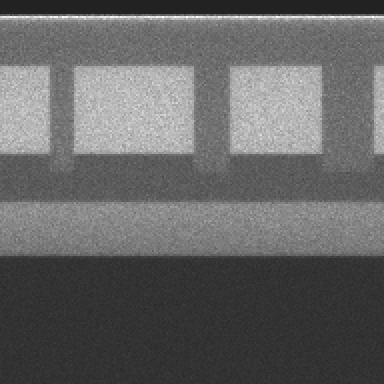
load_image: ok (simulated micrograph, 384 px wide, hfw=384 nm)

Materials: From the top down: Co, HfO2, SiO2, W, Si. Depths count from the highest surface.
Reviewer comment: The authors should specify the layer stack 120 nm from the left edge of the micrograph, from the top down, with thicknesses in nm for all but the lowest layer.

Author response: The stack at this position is Co 50, HfO2 88, SiO2 48, W 54, Si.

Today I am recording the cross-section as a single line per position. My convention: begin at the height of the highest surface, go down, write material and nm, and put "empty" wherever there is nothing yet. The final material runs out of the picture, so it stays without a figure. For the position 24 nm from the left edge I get Co 50, HfO2 88, SiO2 48, W 54, Si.